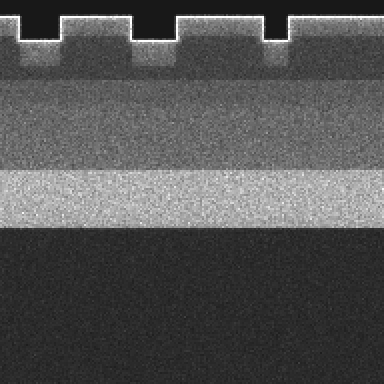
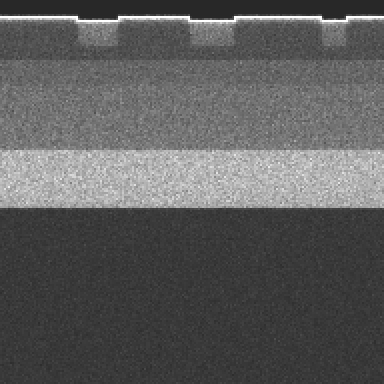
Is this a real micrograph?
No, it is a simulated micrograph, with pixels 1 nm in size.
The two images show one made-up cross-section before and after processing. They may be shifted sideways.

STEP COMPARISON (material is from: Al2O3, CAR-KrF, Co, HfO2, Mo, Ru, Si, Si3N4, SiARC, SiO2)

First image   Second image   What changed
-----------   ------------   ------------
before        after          Ru, removed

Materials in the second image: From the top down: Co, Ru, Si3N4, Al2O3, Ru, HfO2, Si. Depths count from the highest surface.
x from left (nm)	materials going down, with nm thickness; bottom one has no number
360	Si3N4 44, Al2O3 24, Ru 66, HfO2 58, Si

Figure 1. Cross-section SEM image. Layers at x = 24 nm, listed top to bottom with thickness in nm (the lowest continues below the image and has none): Si3N4 44, Al2O3 24, Ru 66, HfO2 58, Si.